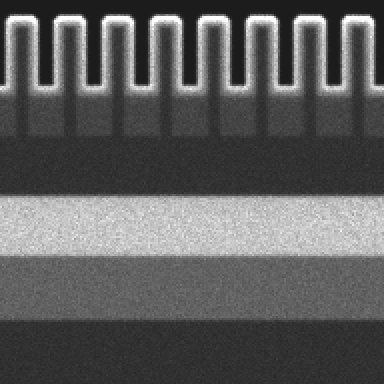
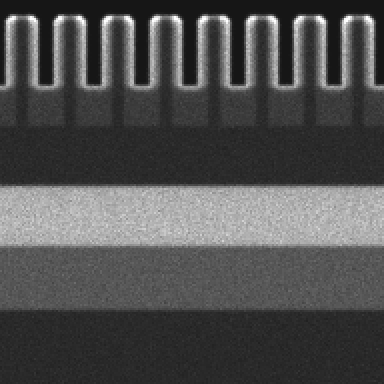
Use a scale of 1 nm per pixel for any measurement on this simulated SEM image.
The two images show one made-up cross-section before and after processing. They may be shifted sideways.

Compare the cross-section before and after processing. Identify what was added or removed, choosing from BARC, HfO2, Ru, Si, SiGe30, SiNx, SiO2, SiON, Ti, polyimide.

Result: SiO2 removed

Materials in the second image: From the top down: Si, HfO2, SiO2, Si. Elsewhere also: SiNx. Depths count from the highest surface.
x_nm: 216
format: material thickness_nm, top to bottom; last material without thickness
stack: Si 170, HfO2 60, SiO2 64, Si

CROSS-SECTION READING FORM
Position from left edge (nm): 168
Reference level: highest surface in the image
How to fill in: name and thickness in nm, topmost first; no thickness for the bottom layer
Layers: Si 170, HfO2 60, SiO2 64, Si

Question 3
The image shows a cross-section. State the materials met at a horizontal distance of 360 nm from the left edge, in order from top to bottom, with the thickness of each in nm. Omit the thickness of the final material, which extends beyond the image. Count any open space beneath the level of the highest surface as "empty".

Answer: Si 170, HfO2 60, SiO2 64, Si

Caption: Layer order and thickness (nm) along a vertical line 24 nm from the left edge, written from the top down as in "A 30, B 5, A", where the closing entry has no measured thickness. Si 170, HfO2 60, SiO2 64, Si